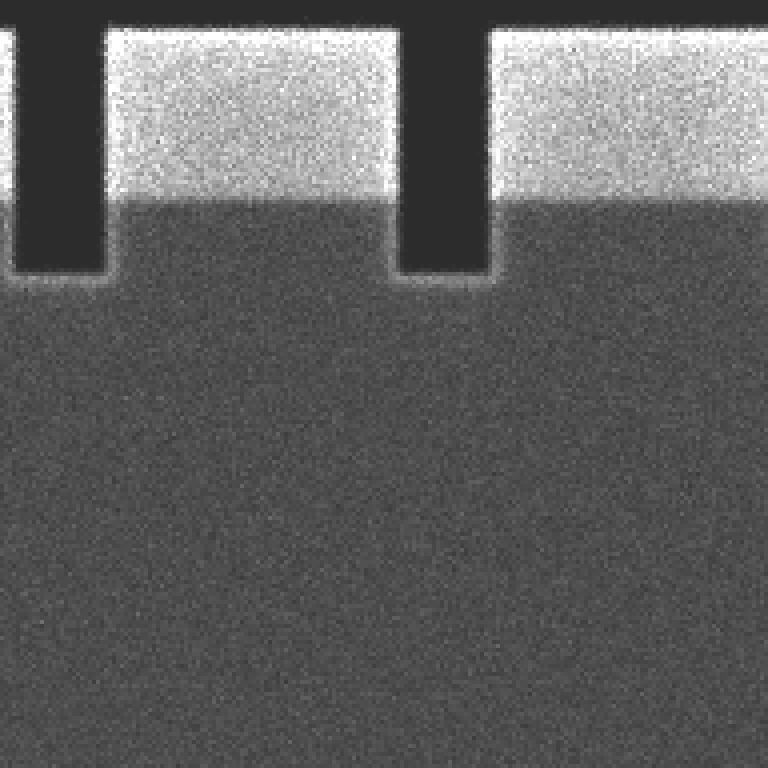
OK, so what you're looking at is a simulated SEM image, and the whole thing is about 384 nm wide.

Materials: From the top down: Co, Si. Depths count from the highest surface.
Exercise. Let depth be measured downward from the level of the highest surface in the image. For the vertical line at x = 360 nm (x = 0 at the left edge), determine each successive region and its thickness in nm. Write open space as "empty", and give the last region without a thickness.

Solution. Co 84, Si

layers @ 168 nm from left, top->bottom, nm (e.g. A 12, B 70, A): Co 84, Si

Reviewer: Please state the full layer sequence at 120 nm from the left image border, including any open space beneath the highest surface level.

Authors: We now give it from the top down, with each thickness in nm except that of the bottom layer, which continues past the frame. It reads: Co 84, Si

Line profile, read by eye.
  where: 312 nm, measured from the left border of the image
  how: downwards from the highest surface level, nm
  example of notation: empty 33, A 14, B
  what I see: Co 84, Si